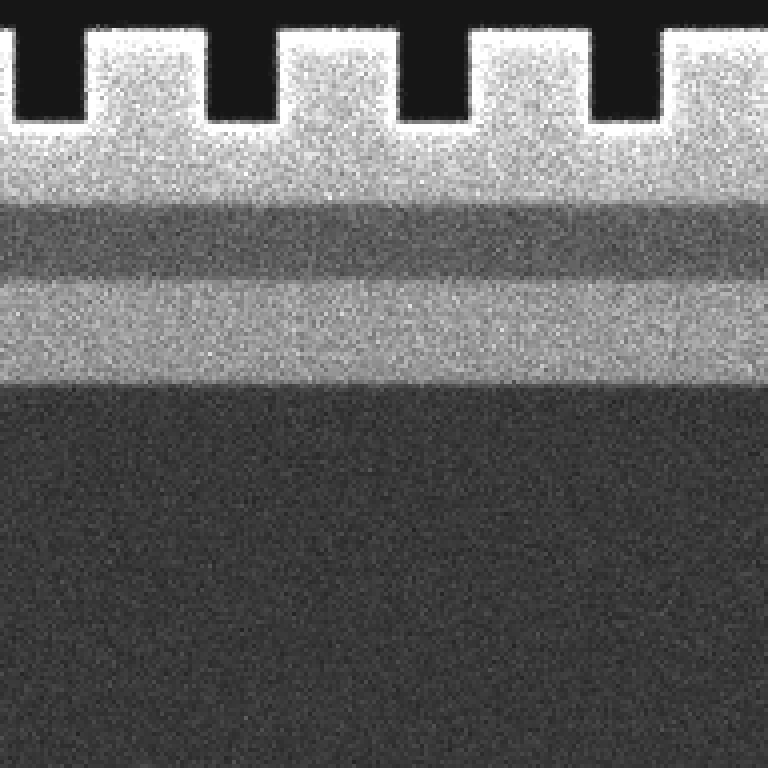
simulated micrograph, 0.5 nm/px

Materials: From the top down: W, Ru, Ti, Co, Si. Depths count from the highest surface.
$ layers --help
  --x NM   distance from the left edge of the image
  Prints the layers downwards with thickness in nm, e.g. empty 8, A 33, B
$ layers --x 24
empty 46, Ru 40, Ti 38, Co 52, Si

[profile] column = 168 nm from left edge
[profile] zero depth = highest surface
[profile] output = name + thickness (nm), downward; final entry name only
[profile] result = W 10, Ru 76, Ti 38, Co 52, Si